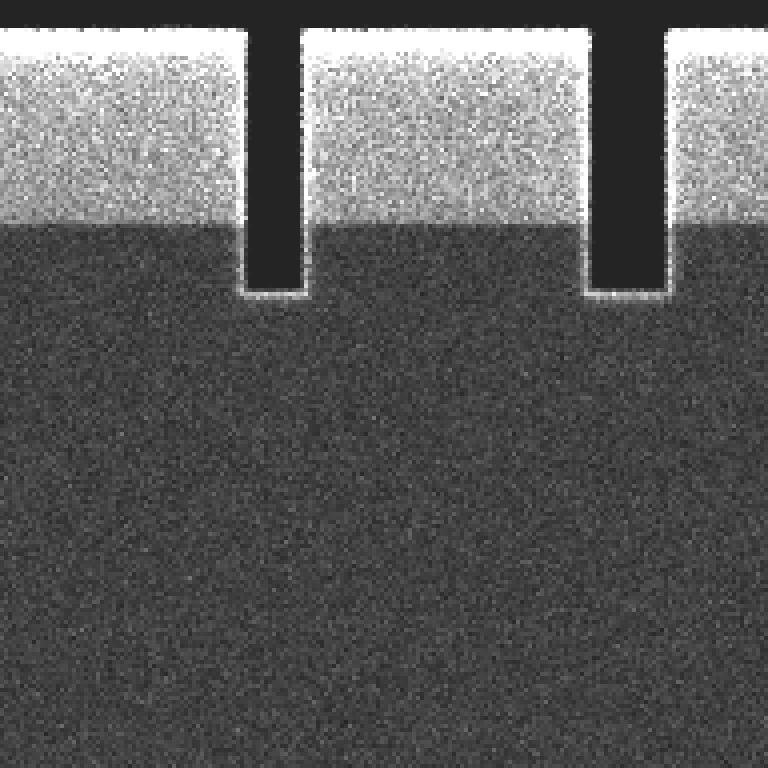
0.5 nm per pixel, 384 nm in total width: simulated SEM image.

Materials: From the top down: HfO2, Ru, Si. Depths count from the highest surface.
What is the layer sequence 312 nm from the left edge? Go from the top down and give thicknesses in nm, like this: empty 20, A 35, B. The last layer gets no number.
empty 130, Si